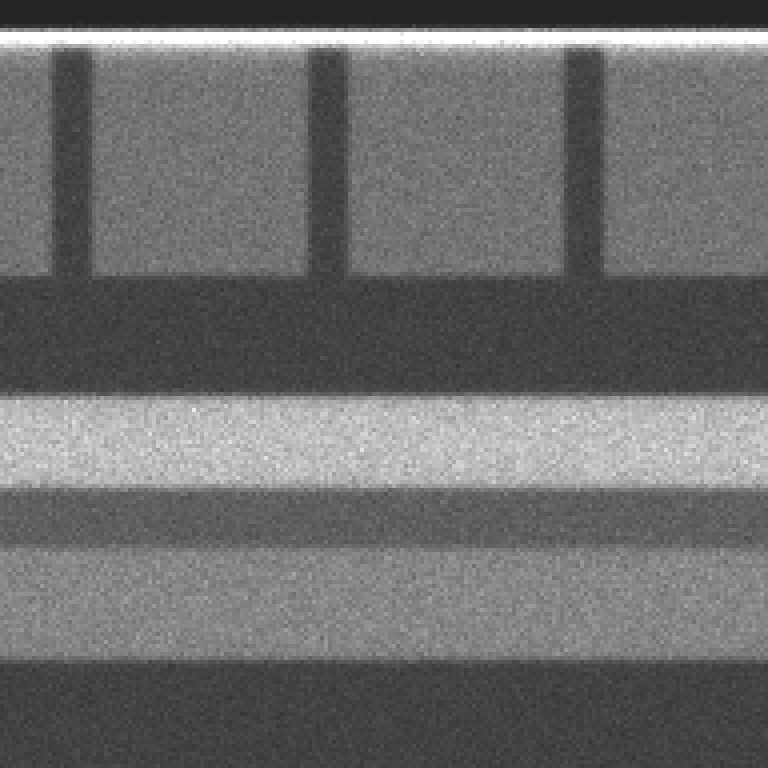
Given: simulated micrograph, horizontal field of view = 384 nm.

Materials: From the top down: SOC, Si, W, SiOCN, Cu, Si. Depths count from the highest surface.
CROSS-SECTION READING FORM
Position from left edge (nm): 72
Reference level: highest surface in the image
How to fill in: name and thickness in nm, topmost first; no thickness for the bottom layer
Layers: SOC 122, Si 60, W 46, SiOCN 30, Cu 56, Si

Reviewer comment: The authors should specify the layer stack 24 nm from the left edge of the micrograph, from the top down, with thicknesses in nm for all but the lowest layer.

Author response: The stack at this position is SOC 122, Si 60, W 46, SiOCN 30, Cu 56, Si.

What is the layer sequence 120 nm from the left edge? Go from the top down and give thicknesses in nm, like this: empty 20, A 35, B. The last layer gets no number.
SOC 122, Si 60, W 46, SiOCN 30, Cu 56, Si